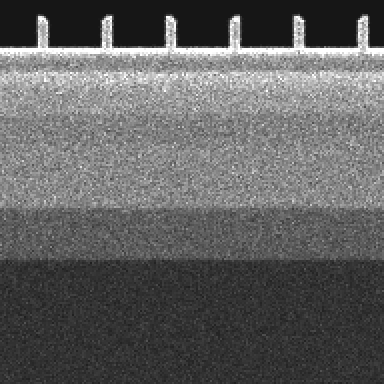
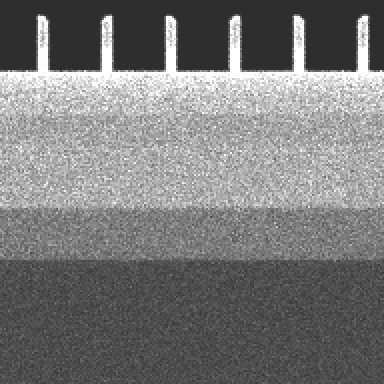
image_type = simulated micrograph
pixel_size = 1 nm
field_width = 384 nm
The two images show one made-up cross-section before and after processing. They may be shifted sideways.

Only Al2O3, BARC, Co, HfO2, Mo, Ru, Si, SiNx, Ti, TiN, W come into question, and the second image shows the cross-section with Al2O3 removed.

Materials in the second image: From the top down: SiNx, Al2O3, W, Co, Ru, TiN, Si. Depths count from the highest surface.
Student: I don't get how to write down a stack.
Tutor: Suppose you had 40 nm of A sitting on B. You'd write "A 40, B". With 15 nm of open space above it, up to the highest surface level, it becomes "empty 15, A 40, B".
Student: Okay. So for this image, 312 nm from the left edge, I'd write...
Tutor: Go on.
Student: empty 56, W 42, Co 32, Ru 62, TiN 52, Si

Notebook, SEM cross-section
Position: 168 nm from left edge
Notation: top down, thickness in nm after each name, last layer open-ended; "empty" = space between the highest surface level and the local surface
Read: SiNx 32, Al2O3 24, W 42, Co 32, Ru 62, TiN 52, Si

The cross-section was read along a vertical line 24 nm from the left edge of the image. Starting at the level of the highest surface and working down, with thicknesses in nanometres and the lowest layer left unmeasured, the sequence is empty 56, W 42, Co 32, Ru 62, TiN 52, Si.